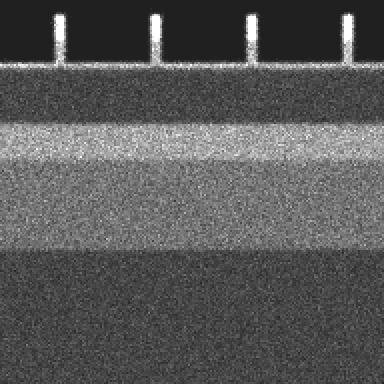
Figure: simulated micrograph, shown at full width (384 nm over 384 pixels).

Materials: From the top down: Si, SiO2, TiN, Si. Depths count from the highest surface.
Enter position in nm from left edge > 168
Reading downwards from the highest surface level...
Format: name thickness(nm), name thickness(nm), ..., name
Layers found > empty 48, Si 60, SiO2 36, TiN 90, Si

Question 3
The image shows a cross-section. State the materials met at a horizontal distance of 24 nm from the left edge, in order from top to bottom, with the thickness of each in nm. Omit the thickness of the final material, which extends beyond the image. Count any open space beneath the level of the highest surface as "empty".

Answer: empty 48, Si 60, SiO2 36, TiN 90, Si